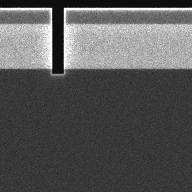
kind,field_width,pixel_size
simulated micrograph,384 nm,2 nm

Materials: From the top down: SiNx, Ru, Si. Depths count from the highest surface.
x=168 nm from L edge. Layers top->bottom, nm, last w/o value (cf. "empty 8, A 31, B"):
SiNx 32, Ru 90, Si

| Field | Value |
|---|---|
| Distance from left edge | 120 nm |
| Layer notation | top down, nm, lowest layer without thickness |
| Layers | empty 132, Si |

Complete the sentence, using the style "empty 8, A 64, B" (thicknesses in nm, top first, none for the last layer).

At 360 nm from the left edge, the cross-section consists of SiNx 32, Ru 90, Si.